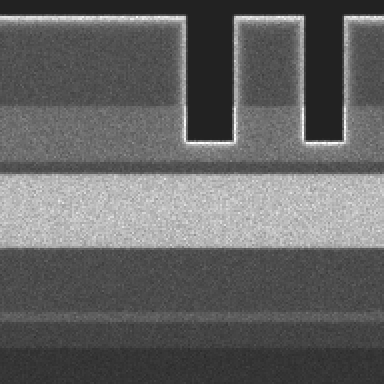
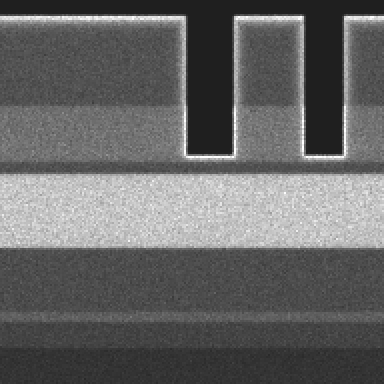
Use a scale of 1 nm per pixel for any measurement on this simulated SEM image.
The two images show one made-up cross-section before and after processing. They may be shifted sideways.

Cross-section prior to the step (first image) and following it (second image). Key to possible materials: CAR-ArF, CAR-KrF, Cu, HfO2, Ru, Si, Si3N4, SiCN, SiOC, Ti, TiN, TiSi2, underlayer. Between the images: Ru was removed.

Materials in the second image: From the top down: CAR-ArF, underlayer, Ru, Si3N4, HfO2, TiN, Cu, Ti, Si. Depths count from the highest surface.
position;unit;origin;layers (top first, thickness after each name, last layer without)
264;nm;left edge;CAR-ArF 62, underlayer 28, Ru 56, Si3N4 12, HfO2 74, TiN 64, Cu 10, Ti 26, Si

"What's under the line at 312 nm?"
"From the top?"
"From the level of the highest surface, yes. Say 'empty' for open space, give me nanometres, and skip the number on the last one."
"empty 140, Ru 6, Si3N4 12, HfO2 74, TiN 64, Cu 10, Ti 26, Si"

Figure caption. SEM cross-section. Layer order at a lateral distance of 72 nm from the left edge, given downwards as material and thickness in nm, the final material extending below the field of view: CAR-ArF 62, underlayer 28, Ru 56, Si3N4 12, HfO2 74, TiN 64, Cu 10, Ti 26, Si